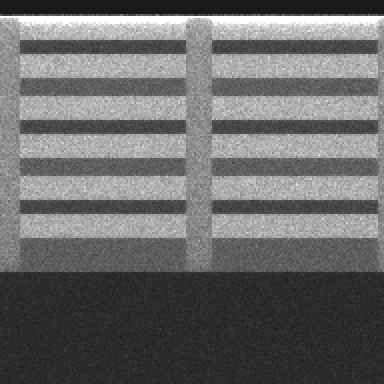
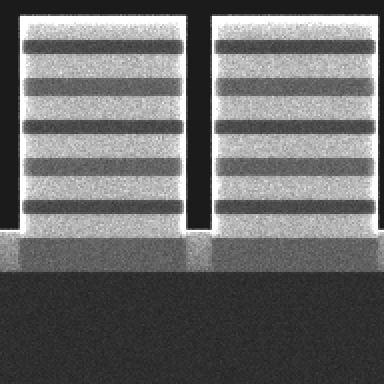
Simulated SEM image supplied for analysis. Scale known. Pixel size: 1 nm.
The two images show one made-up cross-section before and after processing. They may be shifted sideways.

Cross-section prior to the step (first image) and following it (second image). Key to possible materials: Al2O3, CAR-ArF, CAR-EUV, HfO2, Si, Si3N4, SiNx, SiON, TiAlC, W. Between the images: W was removed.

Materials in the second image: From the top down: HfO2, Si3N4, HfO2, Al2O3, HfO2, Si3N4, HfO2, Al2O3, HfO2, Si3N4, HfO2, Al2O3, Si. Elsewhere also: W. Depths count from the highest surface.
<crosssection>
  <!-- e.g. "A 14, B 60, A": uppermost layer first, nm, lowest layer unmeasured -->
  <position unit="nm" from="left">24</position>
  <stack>HfO2 24, Si3N4 14, HfO2 24, Al2O3 18, HfO2 24, Si3N4 14, HfO2 24, Al2O3 18, HfO2 24, Si3N4 14, HfO2 24, Al2O3 34, Si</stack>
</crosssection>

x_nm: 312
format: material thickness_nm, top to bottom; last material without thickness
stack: HfO2 24, Si3N4 14, HfO2 24, Al2O3 18, HfO2 24, Si3N4 14, HfO2 24, Al2O3 18, HfO2 24, Si3N4 14, HfO2 24, Al2O3 34, Si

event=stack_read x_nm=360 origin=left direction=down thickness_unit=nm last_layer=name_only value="HfO2 24, Si3N4 14, HfO2 24, Al2O3 18, HfO2 24, Si3N4 14, HfO2 24, Al2O3 18, HfO2 24, Si3N4 14, HfO2 24, Al2O3 34, Si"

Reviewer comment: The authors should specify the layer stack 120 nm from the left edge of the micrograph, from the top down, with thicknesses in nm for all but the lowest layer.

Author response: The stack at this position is HfO2 24, Si3N4 14, HfO2 24, Al2O3 18, HfO2 24, Si3N4 14, HfO2 24, Al2O3 18, HfO2 24, Si3N4 14, HfO2 24, Al2O3 34, Si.